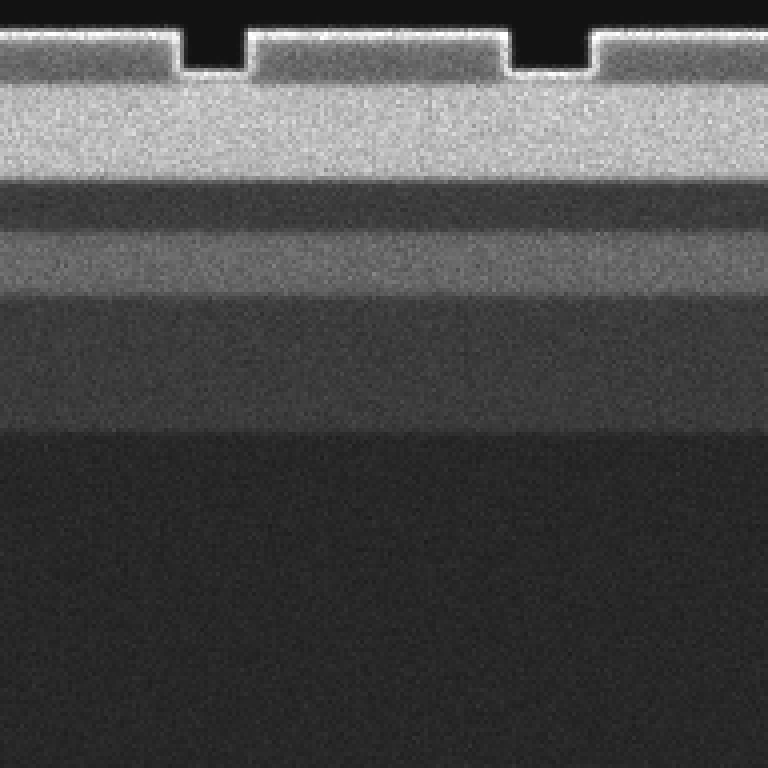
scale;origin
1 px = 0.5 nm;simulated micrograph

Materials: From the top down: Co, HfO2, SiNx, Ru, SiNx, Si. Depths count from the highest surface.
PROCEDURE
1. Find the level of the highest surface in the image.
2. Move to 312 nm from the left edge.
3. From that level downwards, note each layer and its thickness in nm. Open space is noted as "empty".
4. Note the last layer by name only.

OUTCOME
Co 26, HfO2 48, SiNx 26, Ru 32, SiNx 68, Si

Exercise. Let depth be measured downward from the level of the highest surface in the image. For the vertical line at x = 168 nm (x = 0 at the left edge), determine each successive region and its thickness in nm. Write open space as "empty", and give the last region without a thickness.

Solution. Co 26, HfO2 48, SiNx 26, Ru 32, SiNx 68, Si